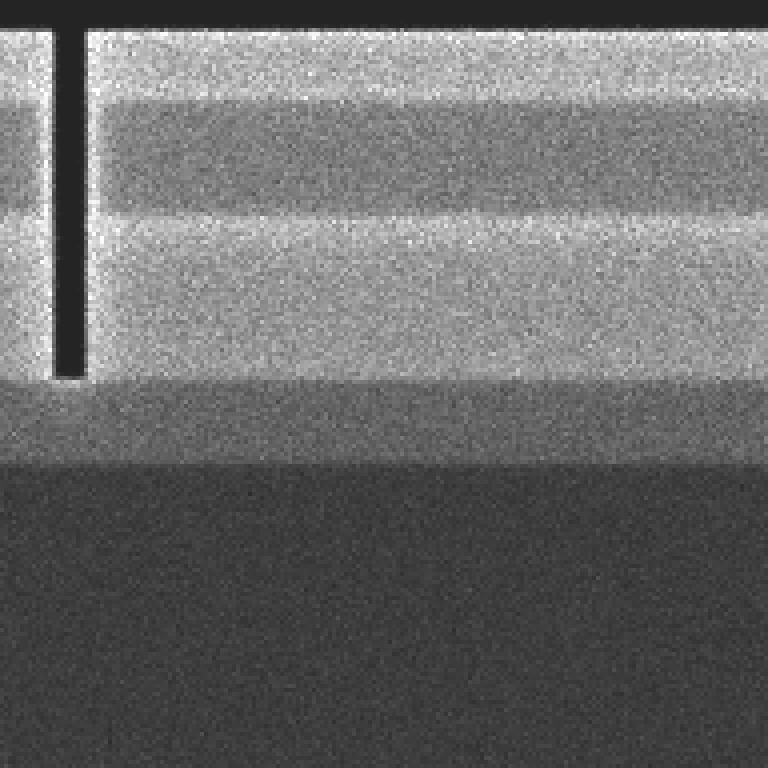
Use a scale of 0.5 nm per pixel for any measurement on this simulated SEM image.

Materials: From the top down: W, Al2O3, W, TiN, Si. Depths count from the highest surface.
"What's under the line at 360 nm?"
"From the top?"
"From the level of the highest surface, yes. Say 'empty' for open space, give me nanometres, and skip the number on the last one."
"W 34, Al2O3 58, W 82, TiN 42, Si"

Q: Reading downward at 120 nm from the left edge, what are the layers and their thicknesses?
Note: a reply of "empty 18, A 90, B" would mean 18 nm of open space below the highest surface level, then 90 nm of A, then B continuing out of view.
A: W 34, Al2O3 58, W 82, TiN 42, Si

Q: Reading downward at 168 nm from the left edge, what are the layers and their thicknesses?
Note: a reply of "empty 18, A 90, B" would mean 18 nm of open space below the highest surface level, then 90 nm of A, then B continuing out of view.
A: W 34, Al2O3 58, W 82, TiN 42, Si